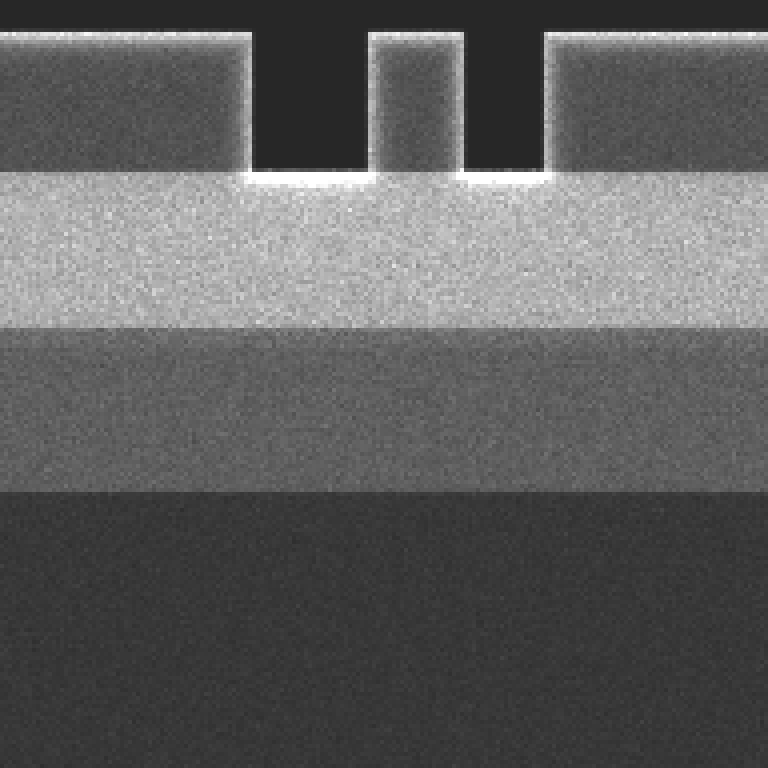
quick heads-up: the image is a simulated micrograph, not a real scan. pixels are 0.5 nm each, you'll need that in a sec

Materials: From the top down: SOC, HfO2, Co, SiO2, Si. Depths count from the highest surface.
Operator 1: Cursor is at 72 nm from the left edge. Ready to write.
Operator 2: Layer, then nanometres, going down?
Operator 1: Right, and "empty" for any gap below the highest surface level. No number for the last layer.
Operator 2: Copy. SOC 70, HfO2 78, Co 10, SiO2 72, Si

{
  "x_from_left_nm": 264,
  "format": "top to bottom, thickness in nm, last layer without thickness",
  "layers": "empty 70, HfO2 78, Co 10, SiO2 72, Si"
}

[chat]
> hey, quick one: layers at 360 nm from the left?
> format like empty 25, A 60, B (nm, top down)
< SOC 70, HfO2 78, Co 10, SiO2 72, Si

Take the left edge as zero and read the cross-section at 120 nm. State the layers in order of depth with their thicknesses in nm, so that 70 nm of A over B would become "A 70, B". SOC 70, HfO2 78, Co 10, SiO2 72, Si